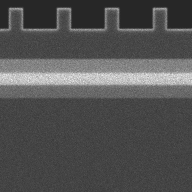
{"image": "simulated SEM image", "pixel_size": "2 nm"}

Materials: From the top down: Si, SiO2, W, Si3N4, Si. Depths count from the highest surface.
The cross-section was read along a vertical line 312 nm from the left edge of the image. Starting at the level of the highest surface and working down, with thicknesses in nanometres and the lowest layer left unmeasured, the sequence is Si 102, SiO2 28, W 24, Si3N4 26, Si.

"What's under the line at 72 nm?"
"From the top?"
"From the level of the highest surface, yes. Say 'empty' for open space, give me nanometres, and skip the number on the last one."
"empty 42, Si 60, SiO2 28, W 24, Si3N4 26, Si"